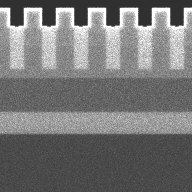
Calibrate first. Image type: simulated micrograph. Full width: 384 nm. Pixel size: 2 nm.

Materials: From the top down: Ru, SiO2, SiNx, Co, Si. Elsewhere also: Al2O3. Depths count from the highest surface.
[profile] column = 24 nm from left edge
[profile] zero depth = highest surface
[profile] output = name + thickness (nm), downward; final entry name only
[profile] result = empty 36, Ru 86, SiO2 18, SiNx 68, Co 44, Si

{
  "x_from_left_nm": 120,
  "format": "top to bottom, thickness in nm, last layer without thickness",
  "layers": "Al2O3 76, SiO2 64, SiNx 68, Co 44, Si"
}